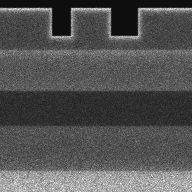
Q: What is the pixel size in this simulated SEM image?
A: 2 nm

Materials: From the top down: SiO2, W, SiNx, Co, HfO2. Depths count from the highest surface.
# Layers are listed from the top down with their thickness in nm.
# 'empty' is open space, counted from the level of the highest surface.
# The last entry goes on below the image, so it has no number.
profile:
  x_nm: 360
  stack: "SiO2 84, W 82, SiNx 70, Co 90, HfO2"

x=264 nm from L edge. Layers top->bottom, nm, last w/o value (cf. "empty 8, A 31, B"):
empty 56, SiO2 28, W 82, SiNx 70, Co 90, HfO2